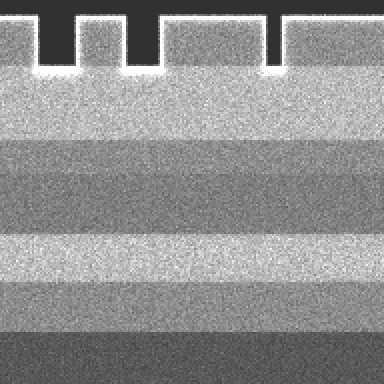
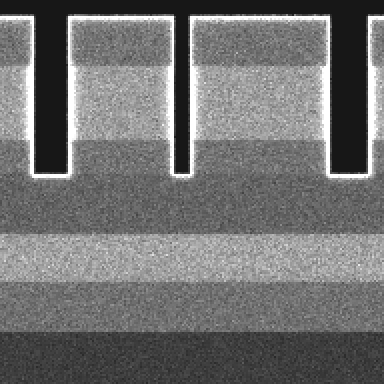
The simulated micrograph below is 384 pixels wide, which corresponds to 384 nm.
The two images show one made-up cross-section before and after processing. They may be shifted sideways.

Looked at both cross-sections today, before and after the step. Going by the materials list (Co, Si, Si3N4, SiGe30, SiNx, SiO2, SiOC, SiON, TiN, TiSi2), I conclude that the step removed Si3N4 and SiO2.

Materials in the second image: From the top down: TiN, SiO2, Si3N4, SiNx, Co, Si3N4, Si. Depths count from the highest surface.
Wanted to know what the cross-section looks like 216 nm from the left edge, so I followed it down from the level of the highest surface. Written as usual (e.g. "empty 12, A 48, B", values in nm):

TiN 50, SiO2 74, Si3N4 34, SiNx 60, Co 48, Si3N4 50, Si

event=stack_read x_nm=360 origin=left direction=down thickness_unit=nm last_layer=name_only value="empty 158, SiNx 60, Co 48, Si3N4 50, Si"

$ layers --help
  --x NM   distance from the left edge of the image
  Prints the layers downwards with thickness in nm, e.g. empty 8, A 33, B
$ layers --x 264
TiN 50, SiO2 74, Si3N4 34, SiNx 60, Co 48, Si3N4 50, Si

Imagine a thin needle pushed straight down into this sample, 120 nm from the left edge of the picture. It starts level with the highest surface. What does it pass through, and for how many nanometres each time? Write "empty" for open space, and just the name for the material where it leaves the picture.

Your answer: TiN 50, SiO2 74, Si3N4 34, SiNx 60, Co 48, Si3N4 50, Si